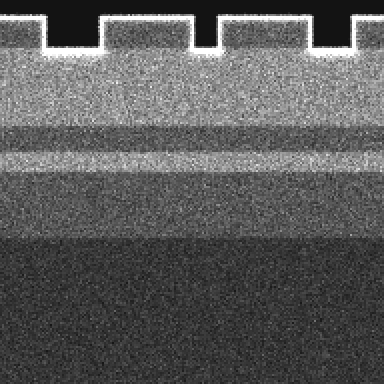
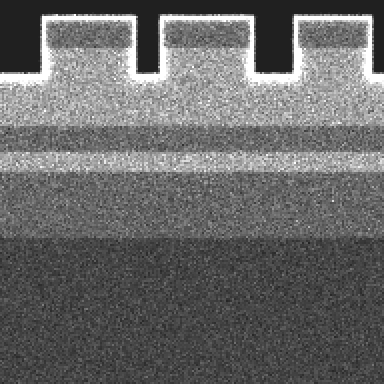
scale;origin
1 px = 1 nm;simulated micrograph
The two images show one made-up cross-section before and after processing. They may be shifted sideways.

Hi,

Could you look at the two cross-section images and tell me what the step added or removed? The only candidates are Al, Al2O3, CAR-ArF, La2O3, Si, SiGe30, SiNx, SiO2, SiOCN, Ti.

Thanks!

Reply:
removed SiO2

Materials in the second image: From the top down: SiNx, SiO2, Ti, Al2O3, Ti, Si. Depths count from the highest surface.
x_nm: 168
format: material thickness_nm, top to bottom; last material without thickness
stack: SiNx 32, SiO2 78, Ti 26, Al2O3 20, Ti 66, Si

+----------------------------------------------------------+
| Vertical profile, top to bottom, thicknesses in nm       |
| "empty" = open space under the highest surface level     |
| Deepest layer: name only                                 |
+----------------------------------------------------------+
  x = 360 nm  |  SiNx 32, SiO2 78, Ti 26, Al2O3 20, Ti 66, Si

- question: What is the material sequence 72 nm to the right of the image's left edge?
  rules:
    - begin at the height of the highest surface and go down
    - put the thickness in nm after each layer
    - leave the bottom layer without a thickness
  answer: SiNx 32, SiO2 78, Ti 26, Al2O3 20, Ti 66, Si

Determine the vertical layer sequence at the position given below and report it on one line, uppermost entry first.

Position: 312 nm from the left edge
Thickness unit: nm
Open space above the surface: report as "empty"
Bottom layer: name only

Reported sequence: SiNx 32, SiO2 78, Ti 26, Al2O3 20, Ti 66, Si